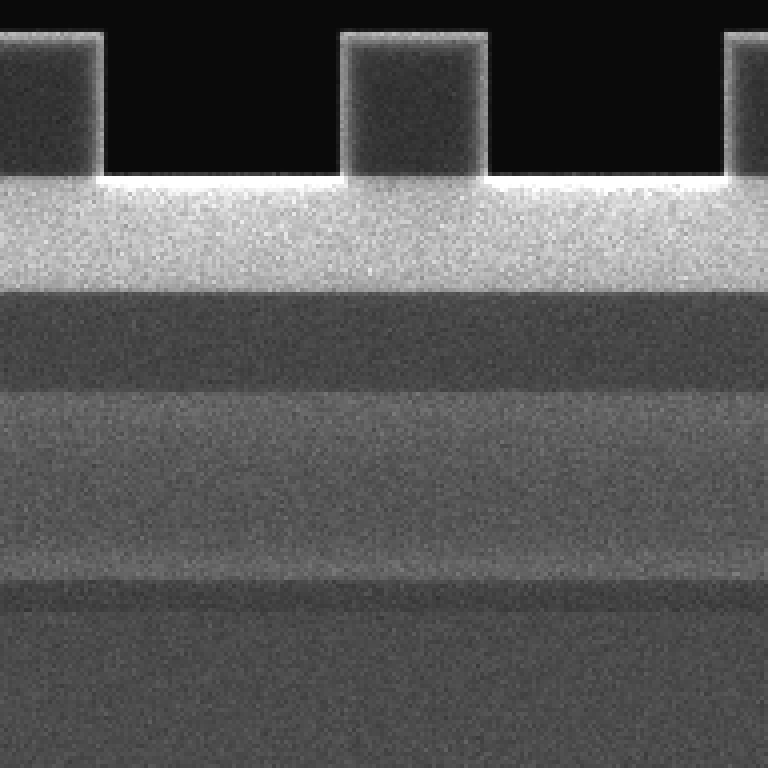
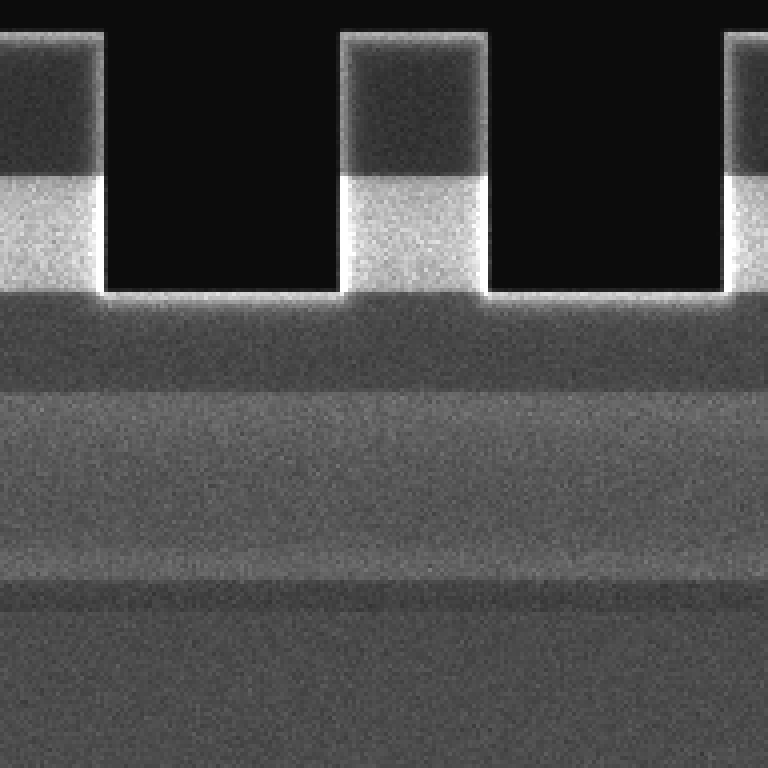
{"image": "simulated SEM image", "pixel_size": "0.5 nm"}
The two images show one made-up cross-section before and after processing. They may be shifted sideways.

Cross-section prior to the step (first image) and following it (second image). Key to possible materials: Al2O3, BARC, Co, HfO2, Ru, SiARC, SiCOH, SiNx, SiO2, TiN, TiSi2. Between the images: HfO2 was removed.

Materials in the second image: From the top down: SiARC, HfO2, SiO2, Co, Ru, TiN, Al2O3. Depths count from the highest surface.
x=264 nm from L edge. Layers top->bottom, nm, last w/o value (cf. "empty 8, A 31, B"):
empty 130, SiO2 50, Co 80, Ru 14, TiN 16, Al2O3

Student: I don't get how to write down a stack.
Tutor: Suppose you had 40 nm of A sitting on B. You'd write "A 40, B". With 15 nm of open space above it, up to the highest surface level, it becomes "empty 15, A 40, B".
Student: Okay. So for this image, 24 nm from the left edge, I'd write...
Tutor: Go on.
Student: SiARC 72, HfO2 58, SiO2 50, Co 80, Ru 14, TiN 16, Al2O3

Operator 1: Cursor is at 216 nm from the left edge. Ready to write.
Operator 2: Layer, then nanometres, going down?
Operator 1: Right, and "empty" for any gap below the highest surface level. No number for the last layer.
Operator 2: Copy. SiARC 72, HfO2 58, SiO2 50, Co 80, Ru 14, TiN 16, Al2O3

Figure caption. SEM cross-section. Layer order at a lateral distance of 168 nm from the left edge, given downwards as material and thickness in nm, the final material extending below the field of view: empty 130, SiO2 50, Co 80, Ru 14, TiN 16, Al2O3